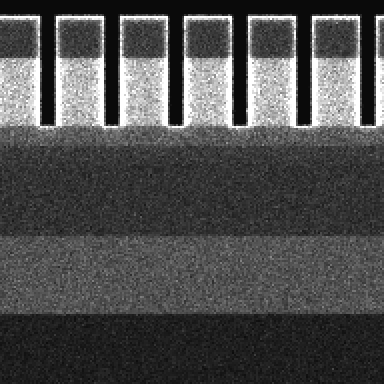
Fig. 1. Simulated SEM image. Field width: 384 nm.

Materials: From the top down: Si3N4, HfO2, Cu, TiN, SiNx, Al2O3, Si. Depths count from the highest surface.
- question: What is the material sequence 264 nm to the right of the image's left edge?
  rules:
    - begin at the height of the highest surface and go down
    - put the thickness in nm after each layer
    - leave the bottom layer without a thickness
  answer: Si3N4 42, HfO2 68, Cu 20, TiN 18, SiNx 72, Al2O3 78, Si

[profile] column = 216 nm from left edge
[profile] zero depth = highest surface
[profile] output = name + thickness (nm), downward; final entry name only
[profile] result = Si3N4 42, HfO2 68, Cu 20, TiN 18, SiNx 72, Al2O3 78, Si